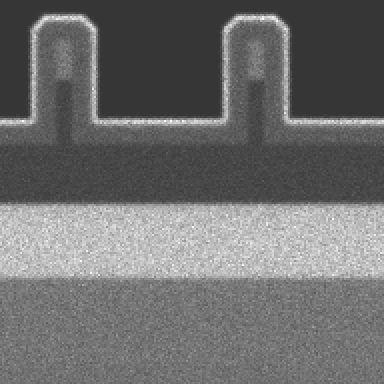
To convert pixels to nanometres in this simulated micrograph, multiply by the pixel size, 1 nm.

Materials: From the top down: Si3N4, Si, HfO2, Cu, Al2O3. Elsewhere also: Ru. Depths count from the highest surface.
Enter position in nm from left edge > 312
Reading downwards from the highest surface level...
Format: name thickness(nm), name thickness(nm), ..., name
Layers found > empty 104, Si3N4 24, Si 60, HfO2 74, Cu 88, Al2O3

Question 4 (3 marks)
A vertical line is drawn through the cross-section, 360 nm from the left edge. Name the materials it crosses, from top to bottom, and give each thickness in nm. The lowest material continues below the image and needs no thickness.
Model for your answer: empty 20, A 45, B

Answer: empty 104, Si3N4 24, Si 60, HfO2 74, Cu 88, Al2O3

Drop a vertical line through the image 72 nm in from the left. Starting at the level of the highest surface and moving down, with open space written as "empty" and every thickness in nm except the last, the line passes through Si3N4 128, Si 60, HfO2 74, Cu 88, Al2O3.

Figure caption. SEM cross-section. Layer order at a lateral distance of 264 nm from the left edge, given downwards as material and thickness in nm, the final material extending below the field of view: Si3N4 128, Si 60, HfO2 74, Cu 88, Al2O3